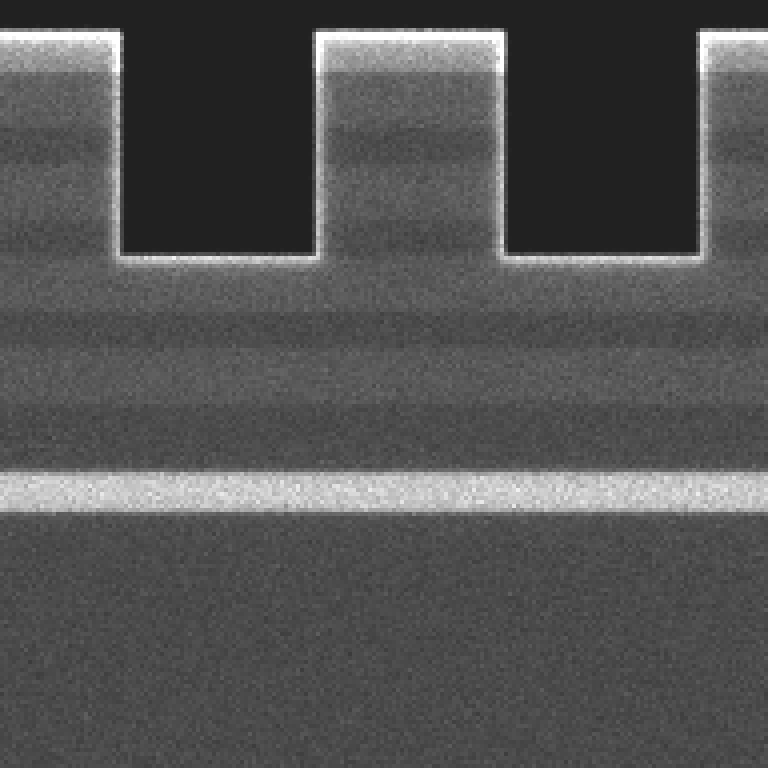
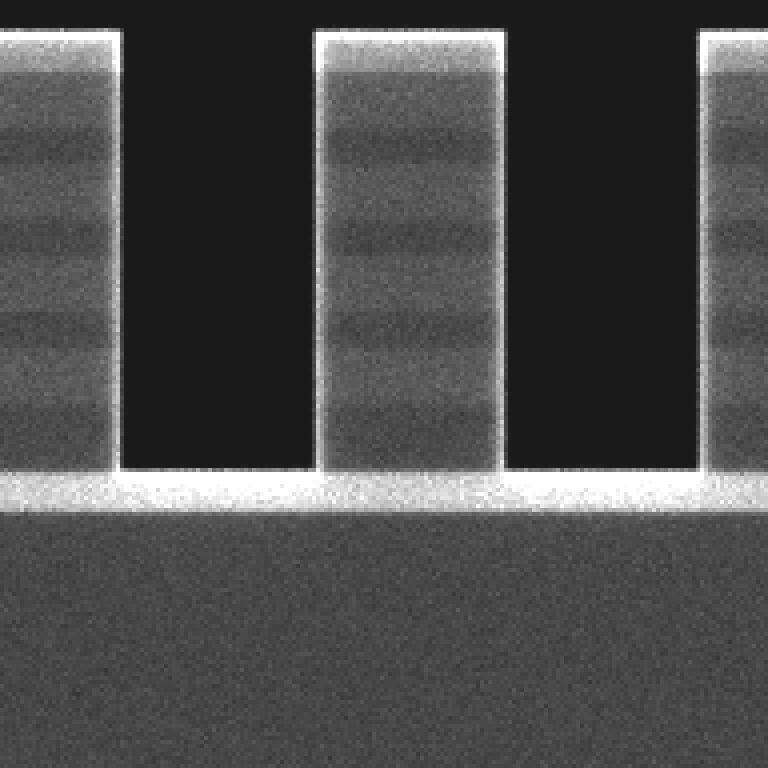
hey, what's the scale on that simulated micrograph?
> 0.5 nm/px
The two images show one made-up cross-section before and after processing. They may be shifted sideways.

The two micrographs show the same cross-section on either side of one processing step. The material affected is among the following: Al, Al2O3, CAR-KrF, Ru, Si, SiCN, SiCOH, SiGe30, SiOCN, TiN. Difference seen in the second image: Si and SiGe30 removed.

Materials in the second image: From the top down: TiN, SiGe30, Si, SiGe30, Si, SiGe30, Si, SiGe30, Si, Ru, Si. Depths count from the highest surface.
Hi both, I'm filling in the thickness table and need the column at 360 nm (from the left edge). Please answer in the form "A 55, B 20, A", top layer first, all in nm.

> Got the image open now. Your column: TiN 20, SiGe30 28, Si 18, SiGe30 28, Si 18, SiGe30 28, Si 18, SiGe30 28, Si 34, Ru 20, Si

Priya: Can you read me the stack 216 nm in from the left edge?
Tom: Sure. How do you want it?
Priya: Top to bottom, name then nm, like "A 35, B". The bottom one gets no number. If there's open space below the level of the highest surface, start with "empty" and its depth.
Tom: TiN 20, SiGe30 28, Si 18, SiGe30 28, Si 18, SiGe30 28, Si 18, SiGe30 28, Si 34, Ru 20, Si